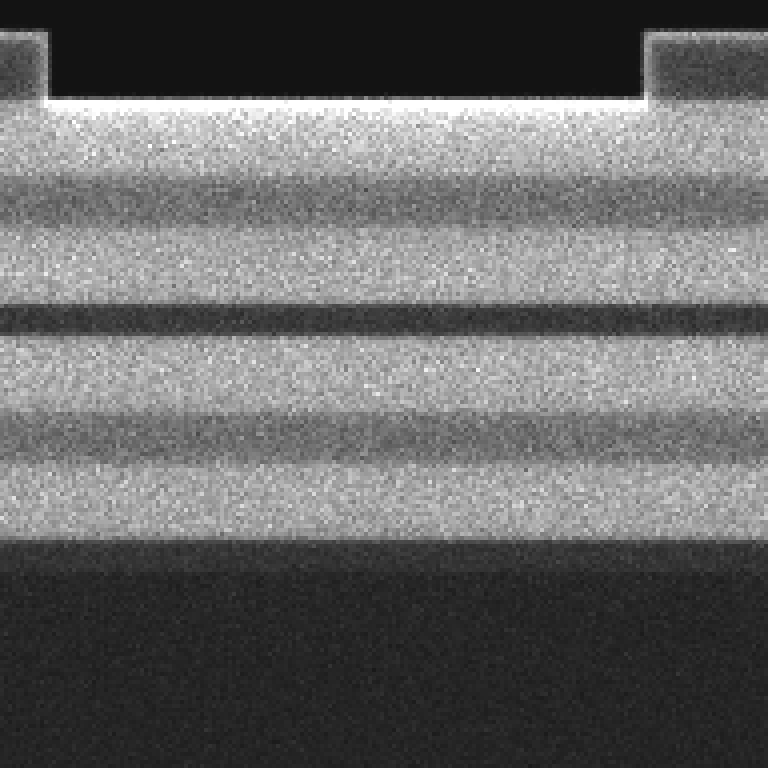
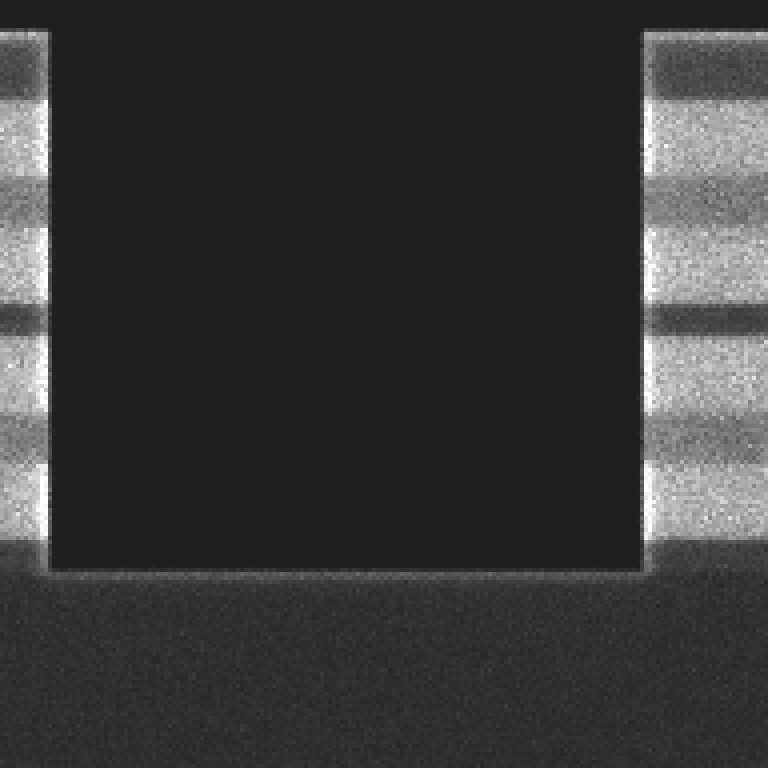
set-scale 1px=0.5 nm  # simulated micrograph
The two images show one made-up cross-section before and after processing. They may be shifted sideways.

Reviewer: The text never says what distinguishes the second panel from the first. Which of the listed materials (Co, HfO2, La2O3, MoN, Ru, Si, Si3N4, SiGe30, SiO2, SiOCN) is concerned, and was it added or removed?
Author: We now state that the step removed HfO2 and Ru and SiOCN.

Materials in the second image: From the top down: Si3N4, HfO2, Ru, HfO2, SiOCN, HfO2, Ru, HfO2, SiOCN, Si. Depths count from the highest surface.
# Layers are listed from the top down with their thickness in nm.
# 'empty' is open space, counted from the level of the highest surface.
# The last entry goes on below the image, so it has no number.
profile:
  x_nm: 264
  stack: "empty 270, Si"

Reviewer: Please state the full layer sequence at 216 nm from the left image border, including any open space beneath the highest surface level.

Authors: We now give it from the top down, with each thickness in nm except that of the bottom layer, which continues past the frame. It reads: empty 270, Si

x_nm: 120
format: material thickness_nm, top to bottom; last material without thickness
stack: empty 270, Si